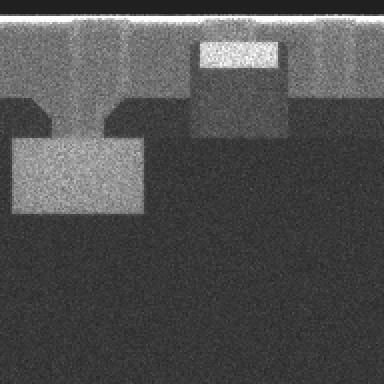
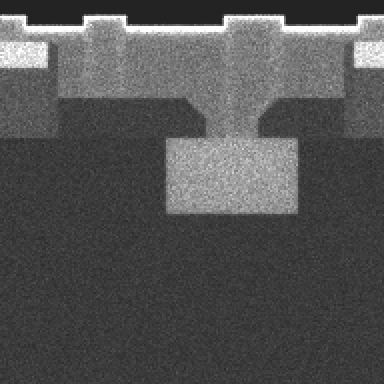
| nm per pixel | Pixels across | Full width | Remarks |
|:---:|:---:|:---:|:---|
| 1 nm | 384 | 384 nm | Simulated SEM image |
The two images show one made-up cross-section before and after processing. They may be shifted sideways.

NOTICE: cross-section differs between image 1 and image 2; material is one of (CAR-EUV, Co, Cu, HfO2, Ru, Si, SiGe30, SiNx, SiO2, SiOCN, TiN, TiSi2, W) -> removed: SiO2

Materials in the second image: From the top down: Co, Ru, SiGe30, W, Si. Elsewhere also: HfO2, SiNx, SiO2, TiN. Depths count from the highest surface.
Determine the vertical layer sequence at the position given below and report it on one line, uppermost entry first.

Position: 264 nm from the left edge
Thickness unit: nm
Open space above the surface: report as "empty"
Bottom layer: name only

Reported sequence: Co 80, Ru 16, SiGe30 26, W 76, Si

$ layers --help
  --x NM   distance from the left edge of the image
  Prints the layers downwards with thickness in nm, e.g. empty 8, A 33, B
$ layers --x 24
Ru 26, HfO2 26, TiN 70, Si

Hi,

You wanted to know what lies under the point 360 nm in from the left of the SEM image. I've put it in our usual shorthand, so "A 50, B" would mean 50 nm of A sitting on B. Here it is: Ru 26, HfO2 26, TiN 70, Si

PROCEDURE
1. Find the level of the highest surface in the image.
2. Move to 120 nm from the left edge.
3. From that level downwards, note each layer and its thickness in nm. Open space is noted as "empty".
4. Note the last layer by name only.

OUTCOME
Ru 82, SiGe30 40, Si